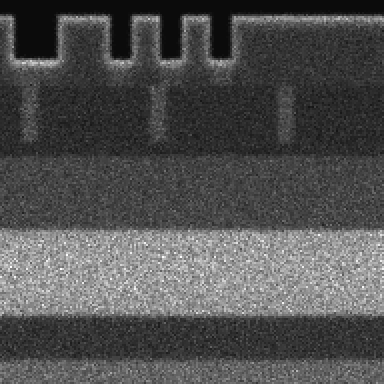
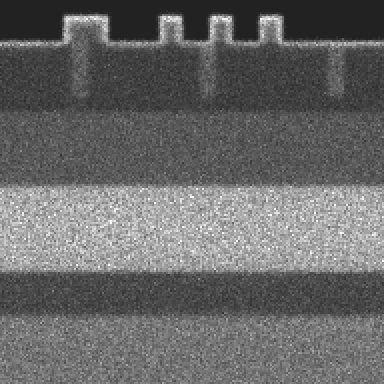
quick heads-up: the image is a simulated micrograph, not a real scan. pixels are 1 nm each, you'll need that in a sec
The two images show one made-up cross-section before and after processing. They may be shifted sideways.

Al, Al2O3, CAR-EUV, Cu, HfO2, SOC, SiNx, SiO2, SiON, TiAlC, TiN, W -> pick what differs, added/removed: SOC removed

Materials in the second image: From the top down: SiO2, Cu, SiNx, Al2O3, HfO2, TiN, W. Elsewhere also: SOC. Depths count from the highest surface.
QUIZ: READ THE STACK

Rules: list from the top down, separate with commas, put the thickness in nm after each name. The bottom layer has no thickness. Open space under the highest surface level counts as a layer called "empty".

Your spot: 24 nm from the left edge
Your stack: empty 26, SiNx 70, Al2O3 74, HfO2 86, TiN 44, W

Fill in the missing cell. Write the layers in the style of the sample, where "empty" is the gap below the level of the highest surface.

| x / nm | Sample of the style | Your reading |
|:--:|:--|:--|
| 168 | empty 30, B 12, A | SiO2 26, SiNx 70, Al2O3 74, HfO2 86, TiN 44, W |